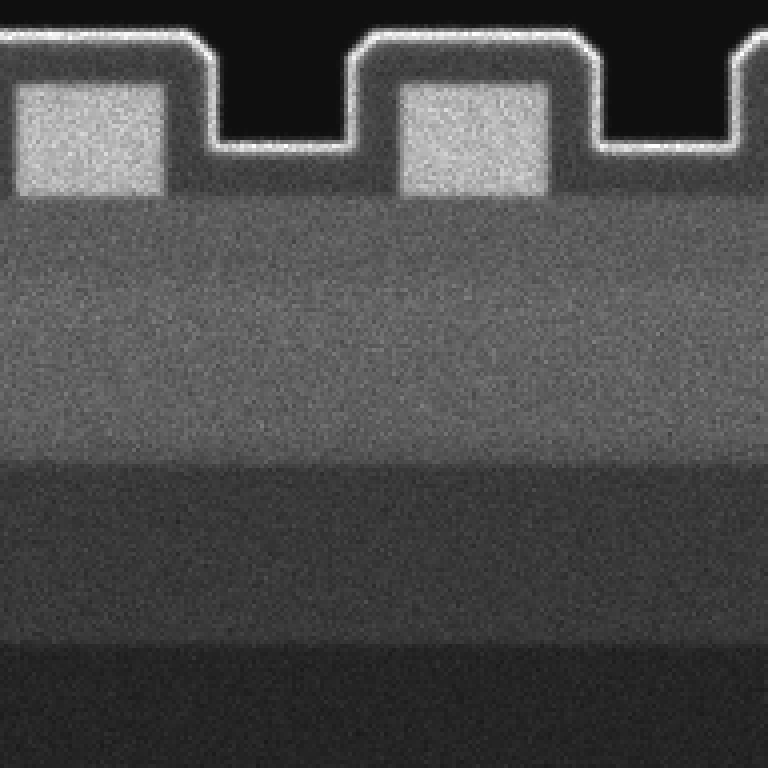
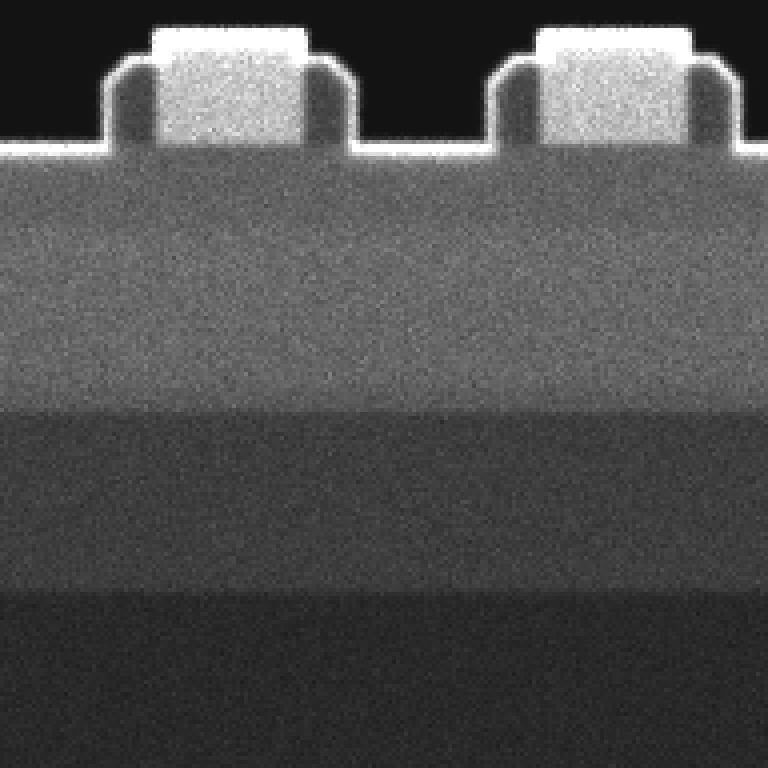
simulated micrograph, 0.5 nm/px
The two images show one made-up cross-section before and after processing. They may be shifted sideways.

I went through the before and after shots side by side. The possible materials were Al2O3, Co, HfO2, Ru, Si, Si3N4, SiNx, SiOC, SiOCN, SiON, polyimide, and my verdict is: removed, Si3N4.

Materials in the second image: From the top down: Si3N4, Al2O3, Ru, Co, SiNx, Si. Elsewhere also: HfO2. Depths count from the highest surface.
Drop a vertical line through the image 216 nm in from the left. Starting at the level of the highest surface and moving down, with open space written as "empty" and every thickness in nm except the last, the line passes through empty 56, Al2O3 42, Ru 80, Co 12, SiNx 90, Si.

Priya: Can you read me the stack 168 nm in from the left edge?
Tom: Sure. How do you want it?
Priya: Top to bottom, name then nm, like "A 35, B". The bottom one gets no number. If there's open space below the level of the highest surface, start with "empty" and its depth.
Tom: empty 16, Si3N4 40, Al2O3 42, Ru 80, Co 12, SiNx 90, Si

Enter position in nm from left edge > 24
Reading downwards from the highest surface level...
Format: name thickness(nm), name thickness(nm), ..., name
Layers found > empty 56, Al2O3 42, Ru 80, Co 12, SiNx 90, Si